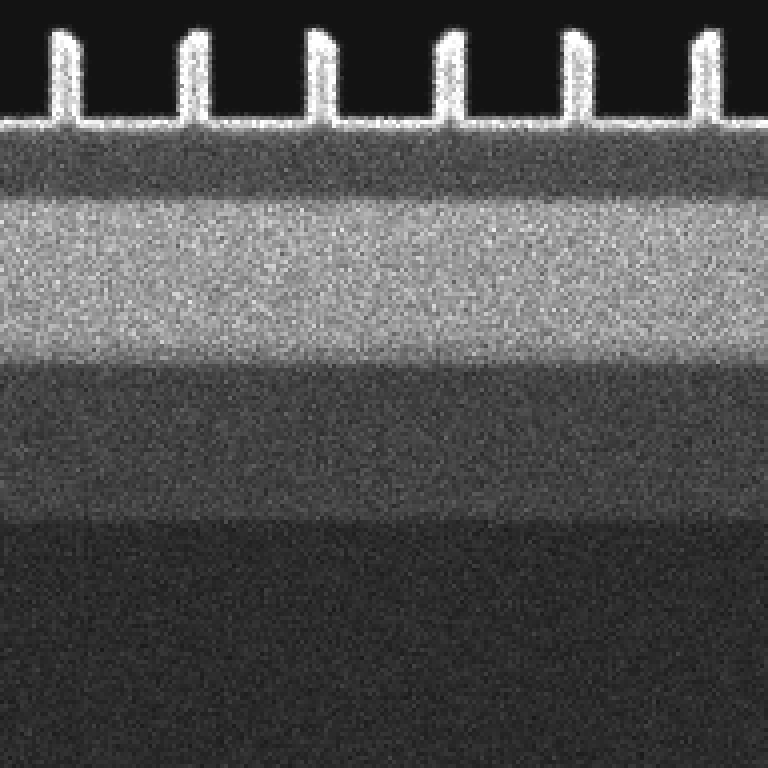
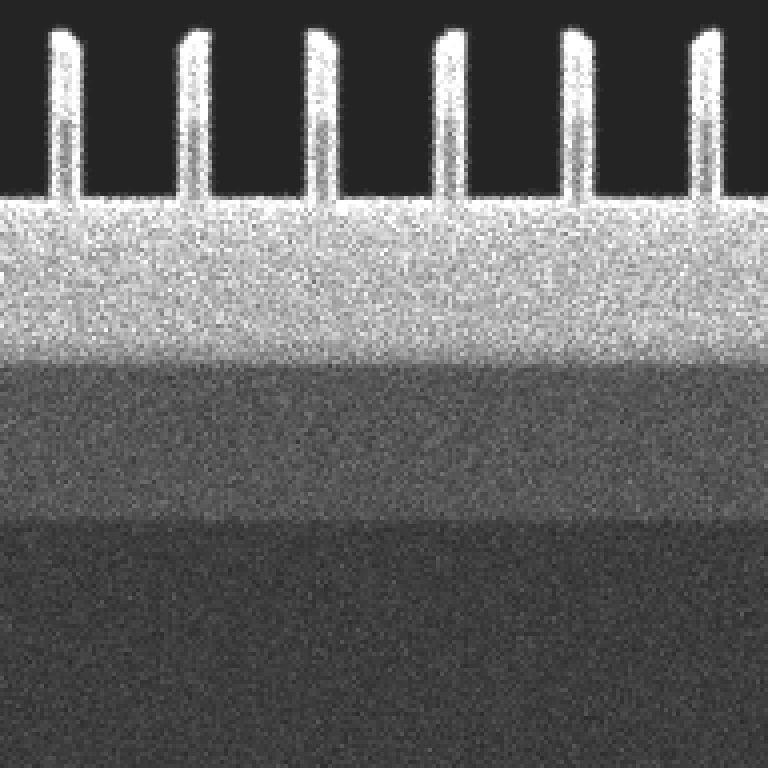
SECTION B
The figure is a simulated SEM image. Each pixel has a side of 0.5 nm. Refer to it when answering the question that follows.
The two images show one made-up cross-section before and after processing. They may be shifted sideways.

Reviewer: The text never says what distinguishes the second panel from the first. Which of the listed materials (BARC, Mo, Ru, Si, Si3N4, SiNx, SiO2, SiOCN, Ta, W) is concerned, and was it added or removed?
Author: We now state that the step removed Si3N4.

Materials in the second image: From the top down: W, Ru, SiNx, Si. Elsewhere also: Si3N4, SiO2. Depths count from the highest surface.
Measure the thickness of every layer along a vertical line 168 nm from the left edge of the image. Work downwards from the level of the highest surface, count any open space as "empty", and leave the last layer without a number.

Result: empty 84, W 72, Ru 10, SiNx 78, Si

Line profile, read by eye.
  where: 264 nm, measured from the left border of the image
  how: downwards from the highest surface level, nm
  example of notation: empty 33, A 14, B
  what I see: empty 84, W 72, Ru 10, SiNx 78, Si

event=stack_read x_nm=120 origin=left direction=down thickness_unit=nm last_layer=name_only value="empty 84, W 72, Ru 10, SiNx 78, Si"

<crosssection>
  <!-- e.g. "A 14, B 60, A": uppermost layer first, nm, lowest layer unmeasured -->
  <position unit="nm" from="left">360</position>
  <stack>empty 84, W 72, Ru 10, SiNx 78, Si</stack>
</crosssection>